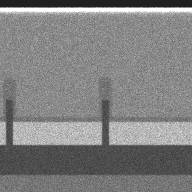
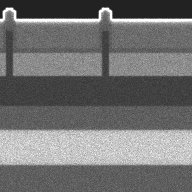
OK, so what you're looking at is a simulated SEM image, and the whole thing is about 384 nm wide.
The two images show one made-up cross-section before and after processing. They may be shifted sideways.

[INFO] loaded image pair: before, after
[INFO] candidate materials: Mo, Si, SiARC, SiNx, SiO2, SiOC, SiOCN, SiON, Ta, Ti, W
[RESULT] removed SiARC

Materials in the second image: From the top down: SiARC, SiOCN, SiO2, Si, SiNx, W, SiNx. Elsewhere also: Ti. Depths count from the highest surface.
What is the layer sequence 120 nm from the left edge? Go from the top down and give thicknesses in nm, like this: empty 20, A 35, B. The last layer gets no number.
empty 22, SiARC 58, SiOCN 10, SiO2 46, Si 60, SiNx 48, W 70, SiNx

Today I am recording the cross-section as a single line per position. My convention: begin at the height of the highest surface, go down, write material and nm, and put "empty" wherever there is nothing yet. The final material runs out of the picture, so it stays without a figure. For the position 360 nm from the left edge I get empty 22, SiARC 58, SiOCN 10, SiO2 46, Si 60, SiNx 48, W 70, SiNx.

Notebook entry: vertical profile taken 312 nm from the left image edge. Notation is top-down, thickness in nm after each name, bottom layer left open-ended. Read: empty 22, SiARC 58, SiOCN 10, SiO2 46, Si 60, SiNx 48, W 70, SiNx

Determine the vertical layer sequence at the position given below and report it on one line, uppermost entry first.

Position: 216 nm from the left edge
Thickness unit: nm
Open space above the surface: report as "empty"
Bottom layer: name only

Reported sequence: SiOCN 10, Ti 36, Si 150, SiNx 48, W 70, SiNx